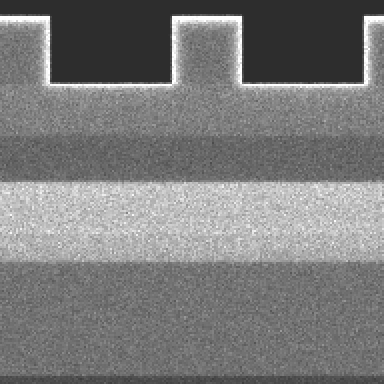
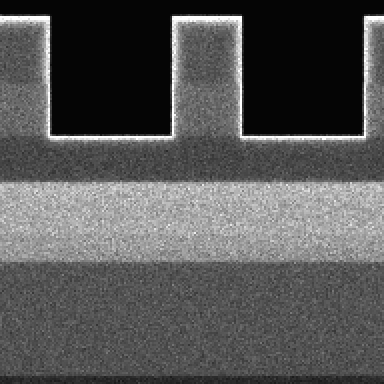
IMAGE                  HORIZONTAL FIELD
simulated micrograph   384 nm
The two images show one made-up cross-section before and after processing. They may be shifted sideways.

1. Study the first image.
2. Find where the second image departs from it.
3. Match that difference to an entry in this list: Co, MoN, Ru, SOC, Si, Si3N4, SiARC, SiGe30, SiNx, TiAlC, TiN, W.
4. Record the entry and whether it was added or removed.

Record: TiN / removed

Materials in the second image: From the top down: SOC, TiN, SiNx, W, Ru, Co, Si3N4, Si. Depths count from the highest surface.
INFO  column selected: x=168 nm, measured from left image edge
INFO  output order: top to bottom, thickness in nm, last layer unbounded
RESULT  empty 120, SiNx 46, W 52, Ru 14, Co 14, Si3N4 114, Si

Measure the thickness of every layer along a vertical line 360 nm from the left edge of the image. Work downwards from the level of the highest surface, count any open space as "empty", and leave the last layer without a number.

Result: empty 120, SiNx 46, W 52, Ru 14, Co 14, Si3N4 114, Si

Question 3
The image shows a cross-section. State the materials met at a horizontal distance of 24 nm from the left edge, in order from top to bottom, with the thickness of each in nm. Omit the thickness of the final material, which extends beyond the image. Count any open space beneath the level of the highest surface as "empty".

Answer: SOC 68, TiN 52, SiNx 46, W 52, Ru 14, Co 14, Si3N4 114, Si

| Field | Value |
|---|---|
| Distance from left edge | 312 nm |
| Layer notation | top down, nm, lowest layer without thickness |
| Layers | empty 120, SiNx 46, W 52, Ru 14, Co 14, Si3N4 114, Si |